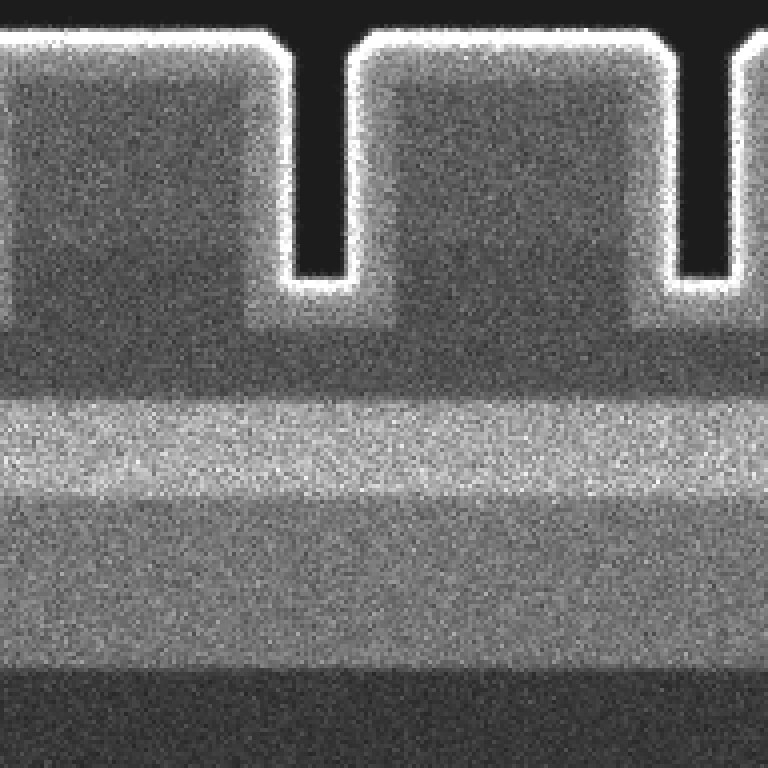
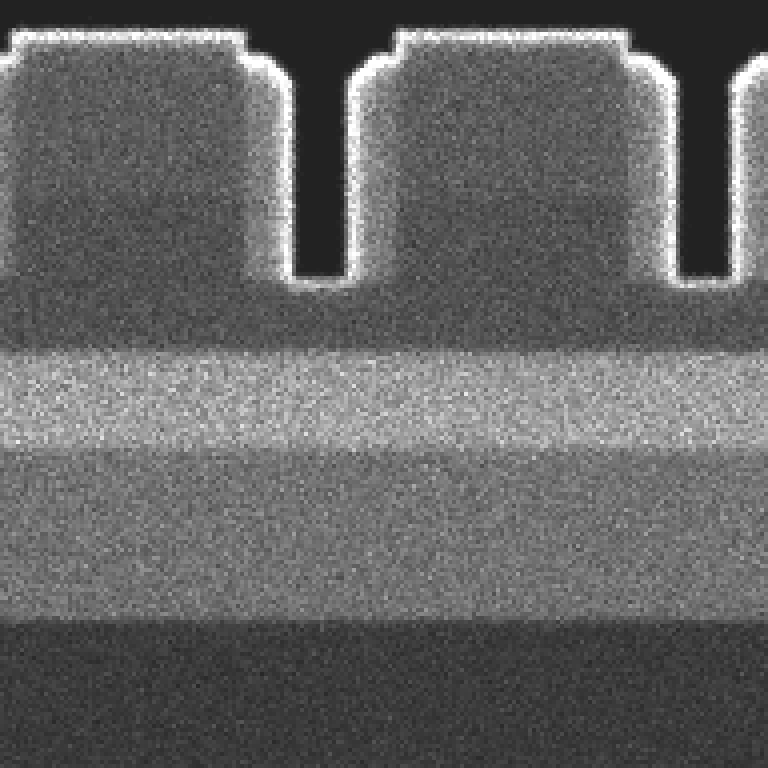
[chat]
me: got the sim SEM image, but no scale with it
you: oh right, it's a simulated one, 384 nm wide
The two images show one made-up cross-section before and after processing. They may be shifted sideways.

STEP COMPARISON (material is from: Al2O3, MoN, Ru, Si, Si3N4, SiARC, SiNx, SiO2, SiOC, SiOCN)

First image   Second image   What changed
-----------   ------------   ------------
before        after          Al2O3, removed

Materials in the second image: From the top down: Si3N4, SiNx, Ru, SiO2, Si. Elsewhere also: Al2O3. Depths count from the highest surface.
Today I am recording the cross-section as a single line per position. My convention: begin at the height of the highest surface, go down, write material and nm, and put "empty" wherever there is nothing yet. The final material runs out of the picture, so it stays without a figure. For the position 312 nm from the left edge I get Si3N4 82, SiNx 78, Ru 48, SiO2 86, Si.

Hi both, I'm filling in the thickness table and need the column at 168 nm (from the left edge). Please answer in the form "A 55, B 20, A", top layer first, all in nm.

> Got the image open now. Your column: empty 124, SiNx 36, Ru 48, SiO2 86, Si